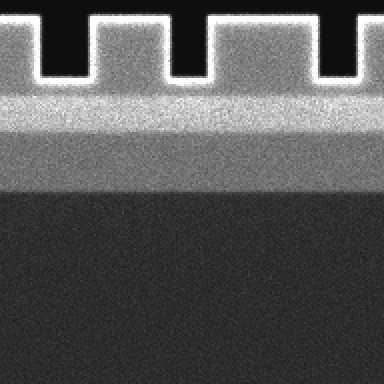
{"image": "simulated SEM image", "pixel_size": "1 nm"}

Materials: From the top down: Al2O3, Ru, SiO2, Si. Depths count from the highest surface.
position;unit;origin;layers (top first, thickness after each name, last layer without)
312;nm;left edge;Al2O3 80, Ru 36, SiO2 60, Si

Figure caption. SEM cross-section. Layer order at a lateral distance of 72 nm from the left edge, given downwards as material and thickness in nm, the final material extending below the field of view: empty 62, Al2O3 18, Ru 36, SiO2 60, Si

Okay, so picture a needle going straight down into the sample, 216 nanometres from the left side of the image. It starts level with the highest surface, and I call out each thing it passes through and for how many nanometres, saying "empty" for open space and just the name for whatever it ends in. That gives Al2O3 80, Ru 36, SiO2 60, Si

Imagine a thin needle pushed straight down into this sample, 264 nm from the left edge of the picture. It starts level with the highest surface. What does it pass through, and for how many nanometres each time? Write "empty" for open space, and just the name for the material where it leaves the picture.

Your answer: Al2O3 80, Ru 36, SiO2 60, Si